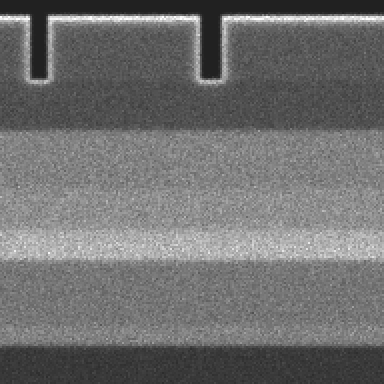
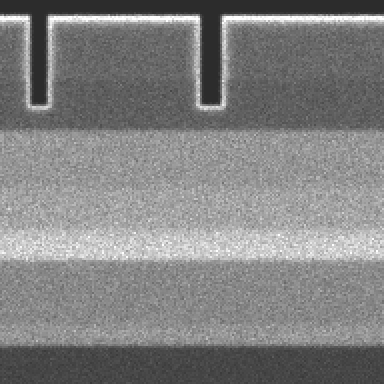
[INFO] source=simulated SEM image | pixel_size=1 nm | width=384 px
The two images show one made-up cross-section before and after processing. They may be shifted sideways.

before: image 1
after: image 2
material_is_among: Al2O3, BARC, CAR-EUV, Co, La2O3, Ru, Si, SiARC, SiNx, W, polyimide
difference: SiNx, removed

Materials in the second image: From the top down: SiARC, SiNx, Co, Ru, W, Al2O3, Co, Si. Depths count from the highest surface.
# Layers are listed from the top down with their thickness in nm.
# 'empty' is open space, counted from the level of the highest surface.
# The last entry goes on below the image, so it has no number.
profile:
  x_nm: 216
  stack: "empty 90, SiNx 24, Co 58, Ru 42, W 30, Al2O3 66, Co 20, Si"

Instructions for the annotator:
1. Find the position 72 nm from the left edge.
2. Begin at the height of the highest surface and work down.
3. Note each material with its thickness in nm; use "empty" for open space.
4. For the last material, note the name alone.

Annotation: SiARC 64, SiNx 50, Co 58, Ru 42, W 30, Al2O3 66, Co 20, Si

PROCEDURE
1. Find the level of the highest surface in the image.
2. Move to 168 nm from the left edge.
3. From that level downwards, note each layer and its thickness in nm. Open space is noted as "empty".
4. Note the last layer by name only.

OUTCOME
SiARC 64, SiNx 50, Co 58, Ru 42, W 30, Al2O3 66, Co 20, Si